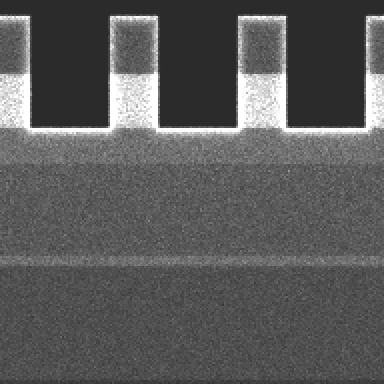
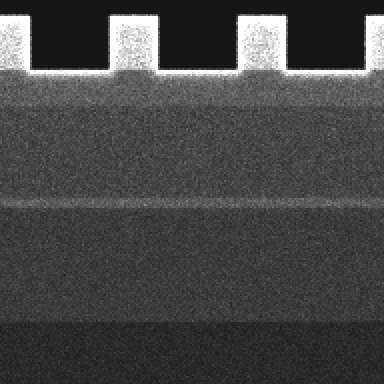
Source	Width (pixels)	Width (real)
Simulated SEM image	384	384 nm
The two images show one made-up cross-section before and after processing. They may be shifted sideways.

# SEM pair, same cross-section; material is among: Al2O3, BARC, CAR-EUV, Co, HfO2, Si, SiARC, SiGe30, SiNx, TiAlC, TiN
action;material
removed;SiARC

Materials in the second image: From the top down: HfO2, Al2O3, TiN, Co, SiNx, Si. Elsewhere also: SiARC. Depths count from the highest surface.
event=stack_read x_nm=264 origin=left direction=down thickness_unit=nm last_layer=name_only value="HfO2 54, Al2O3 36, TiN 92, Co 10, SiNx 114, Si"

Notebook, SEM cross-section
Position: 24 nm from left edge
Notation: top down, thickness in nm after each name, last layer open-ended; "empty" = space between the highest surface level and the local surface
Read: HfO2 54, Al2O3 36, TiN 92, Co 10, SiNx 114, Si